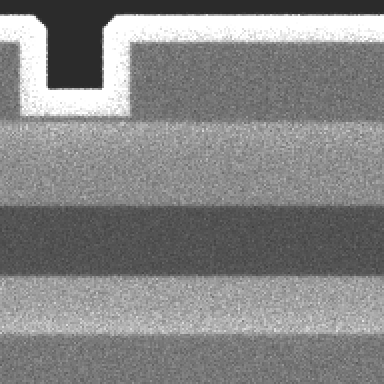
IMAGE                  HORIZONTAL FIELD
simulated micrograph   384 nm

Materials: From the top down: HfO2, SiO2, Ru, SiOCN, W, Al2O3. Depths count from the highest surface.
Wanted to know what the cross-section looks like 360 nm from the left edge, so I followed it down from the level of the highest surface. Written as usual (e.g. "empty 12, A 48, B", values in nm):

HfO2 26, SiO2 80, Ru 84, SiOCN 70, W 58, Al2O3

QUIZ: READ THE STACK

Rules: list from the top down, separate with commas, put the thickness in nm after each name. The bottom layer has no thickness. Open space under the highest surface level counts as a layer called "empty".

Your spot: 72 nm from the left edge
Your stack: empty 74, HfO2 26, SiO2 6, Ru 84, SiOCN 70, W 58, Al2O3